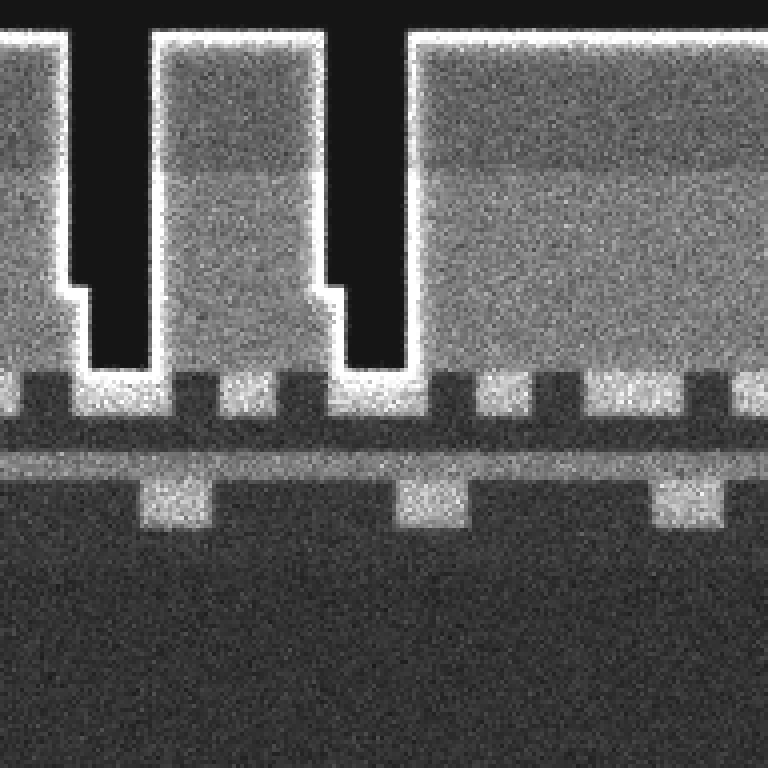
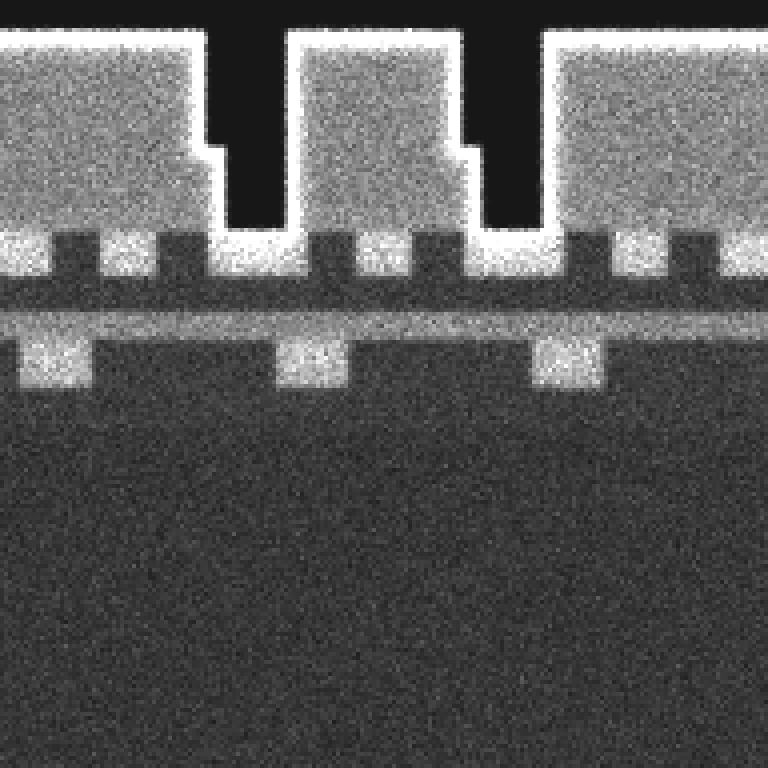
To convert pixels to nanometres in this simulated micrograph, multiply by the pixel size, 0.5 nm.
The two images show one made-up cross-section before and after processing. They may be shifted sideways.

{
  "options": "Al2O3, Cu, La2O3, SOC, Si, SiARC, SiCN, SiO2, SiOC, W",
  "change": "removed",
  "material": "SOC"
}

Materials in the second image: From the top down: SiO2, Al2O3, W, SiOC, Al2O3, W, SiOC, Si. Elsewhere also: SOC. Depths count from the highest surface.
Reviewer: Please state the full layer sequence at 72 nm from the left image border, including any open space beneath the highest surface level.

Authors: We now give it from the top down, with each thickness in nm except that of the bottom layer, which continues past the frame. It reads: SiO2 88, Al2O3 12, W 22, SiOC 18, Al2O3 14, SiOC 44, Si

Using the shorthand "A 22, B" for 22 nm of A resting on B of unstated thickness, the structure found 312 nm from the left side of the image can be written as SiO2 88, Al2O3 12, W 22, SiOC 18, Al2O3 14, SiOC 44, Si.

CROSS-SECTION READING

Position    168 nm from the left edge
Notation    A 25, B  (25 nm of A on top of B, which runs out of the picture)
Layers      SiO2 88, Al2O3 12, SiOC 40, Al2O3 14, W 24, SiOC 20, Si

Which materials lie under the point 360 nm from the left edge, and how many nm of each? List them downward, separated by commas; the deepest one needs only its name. SiO2 88, Al2O3 12, W 22, SiOC 18, Al2O3 14, SiOC 44, Si